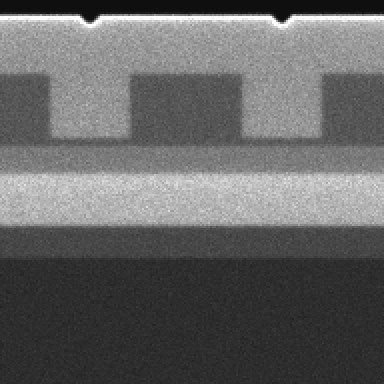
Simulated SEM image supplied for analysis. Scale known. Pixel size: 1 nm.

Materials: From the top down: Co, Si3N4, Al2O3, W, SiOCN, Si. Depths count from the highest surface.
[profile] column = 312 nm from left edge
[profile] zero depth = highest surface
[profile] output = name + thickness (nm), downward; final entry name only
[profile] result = Co 122, Si3N4 8, Al2O3 28, W 52, SiOCN 32, Si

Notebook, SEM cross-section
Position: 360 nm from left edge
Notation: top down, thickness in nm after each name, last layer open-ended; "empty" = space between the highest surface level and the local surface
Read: Co 58, Si3N4 72, Al2O3 28, W 52, SiOCN 32, Si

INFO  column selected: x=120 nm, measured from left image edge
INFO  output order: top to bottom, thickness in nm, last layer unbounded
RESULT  Co 122, Si3N4 8, Al2O3 28, W 52, SiOCN 32, Si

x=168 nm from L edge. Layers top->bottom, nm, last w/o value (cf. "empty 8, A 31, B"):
Co 58, Si3N4 72, Al2O3 28, W 52, SiOCN 32, Si